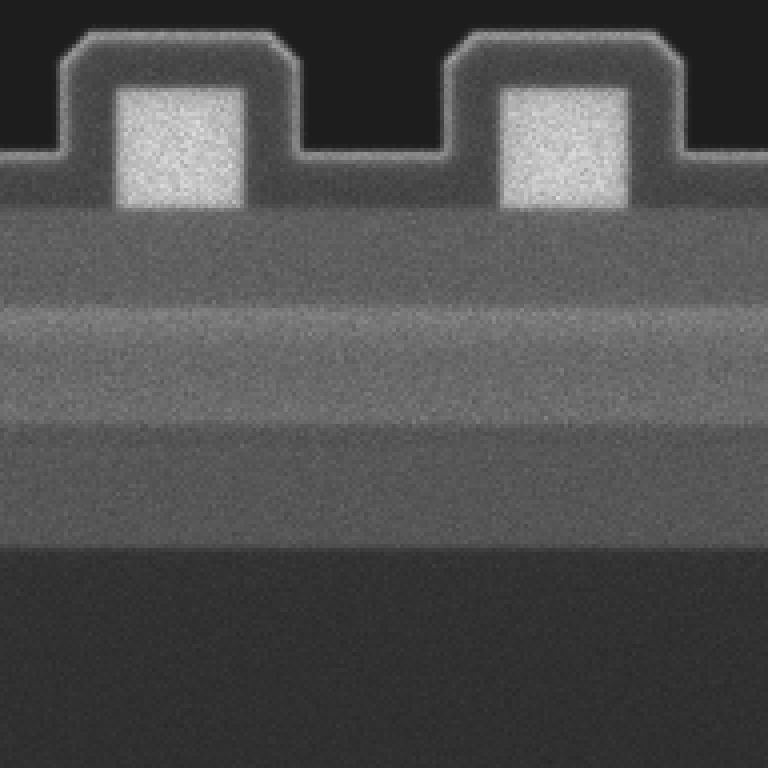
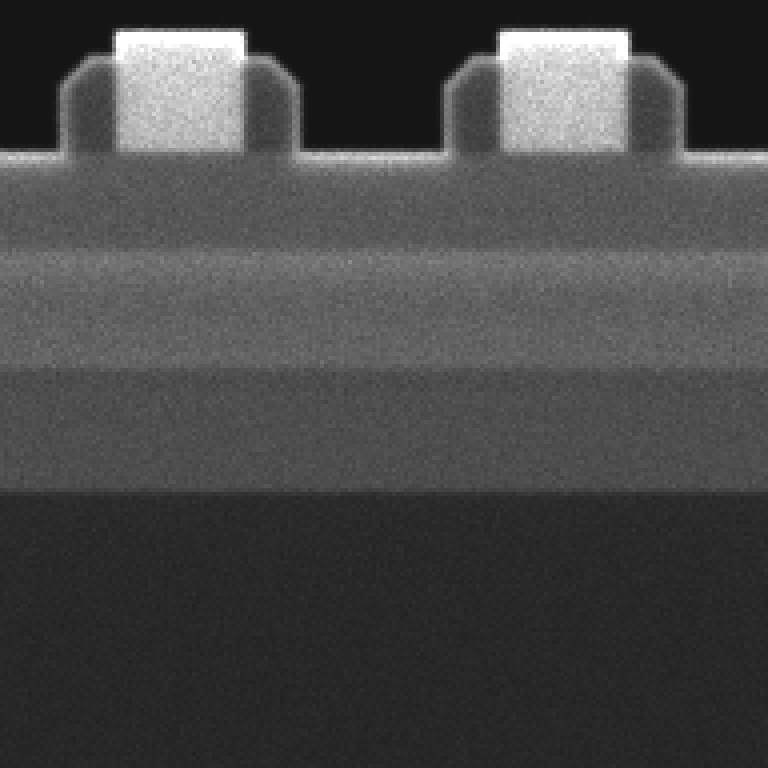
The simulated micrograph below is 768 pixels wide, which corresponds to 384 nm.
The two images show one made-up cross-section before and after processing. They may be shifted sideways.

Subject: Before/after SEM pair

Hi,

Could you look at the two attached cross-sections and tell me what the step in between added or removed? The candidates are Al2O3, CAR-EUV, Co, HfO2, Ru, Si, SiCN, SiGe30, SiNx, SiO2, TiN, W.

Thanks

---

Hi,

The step removed SiNx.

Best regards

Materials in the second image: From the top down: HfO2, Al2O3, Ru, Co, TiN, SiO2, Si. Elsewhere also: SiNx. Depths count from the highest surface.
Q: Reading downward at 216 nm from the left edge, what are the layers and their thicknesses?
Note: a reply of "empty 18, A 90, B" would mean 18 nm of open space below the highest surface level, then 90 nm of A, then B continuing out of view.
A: empty 60, Al2O3 50, Ru 42, Co 16, TiN 12, SiO2 50, Si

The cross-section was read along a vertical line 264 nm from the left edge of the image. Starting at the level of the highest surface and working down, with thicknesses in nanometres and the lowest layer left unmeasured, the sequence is HfO2 60, Al2O3 50, Ru 42, Co 16, TiN 12, SiO2 50, Si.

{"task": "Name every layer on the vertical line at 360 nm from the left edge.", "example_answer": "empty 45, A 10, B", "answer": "empty 60, Al2O3 50, Ru 42, Co 16, TiN 12, SiO2 50, Si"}